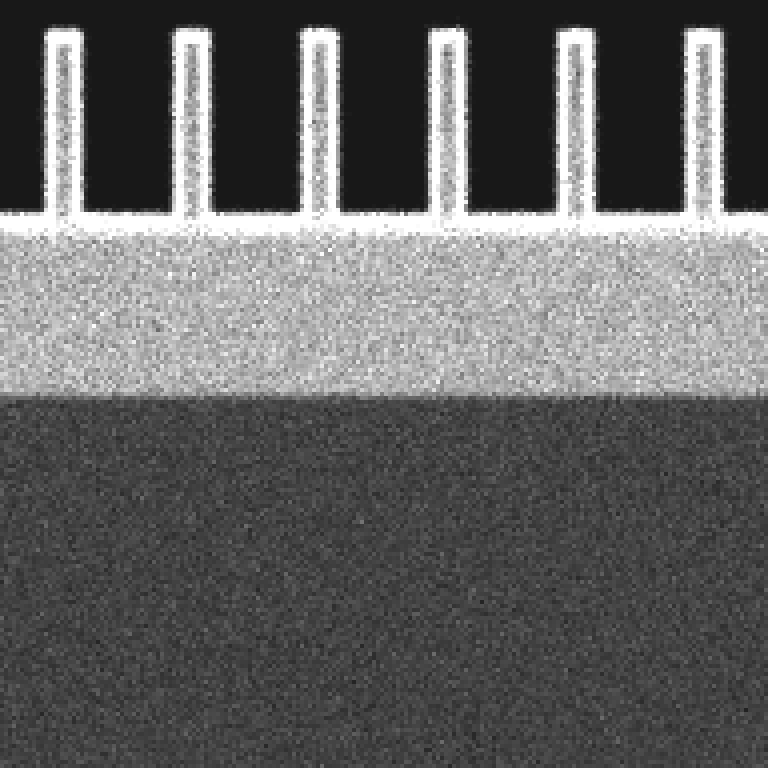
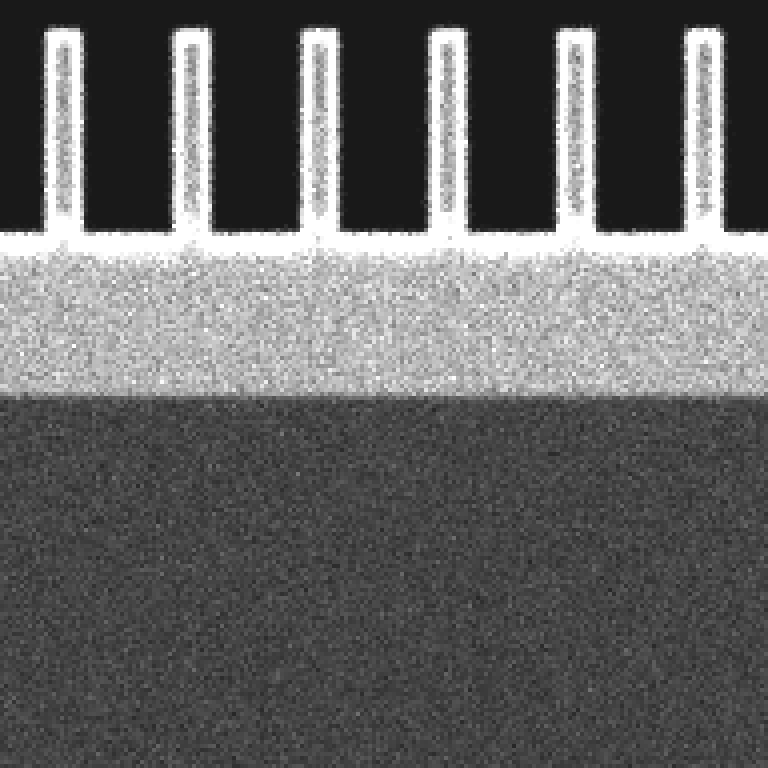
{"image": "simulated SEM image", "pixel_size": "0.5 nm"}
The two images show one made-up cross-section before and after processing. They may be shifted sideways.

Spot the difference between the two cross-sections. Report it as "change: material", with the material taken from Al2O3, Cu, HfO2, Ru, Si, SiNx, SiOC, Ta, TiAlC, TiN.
removed: Ru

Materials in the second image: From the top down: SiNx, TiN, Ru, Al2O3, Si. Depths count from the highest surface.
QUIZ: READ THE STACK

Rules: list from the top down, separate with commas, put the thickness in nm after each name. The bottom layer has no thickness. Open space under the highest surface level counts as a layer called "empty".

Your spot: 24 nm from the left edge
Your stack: SiNx 38, TiN 54, Ru 10, Al2O3 80, Si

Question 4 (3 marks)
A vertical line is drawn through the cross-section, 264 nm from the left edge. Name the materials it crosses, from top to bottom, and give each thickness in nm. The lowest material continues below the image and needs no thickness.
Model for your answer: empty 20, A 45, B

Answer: empty 102, Al2O3 80, Si